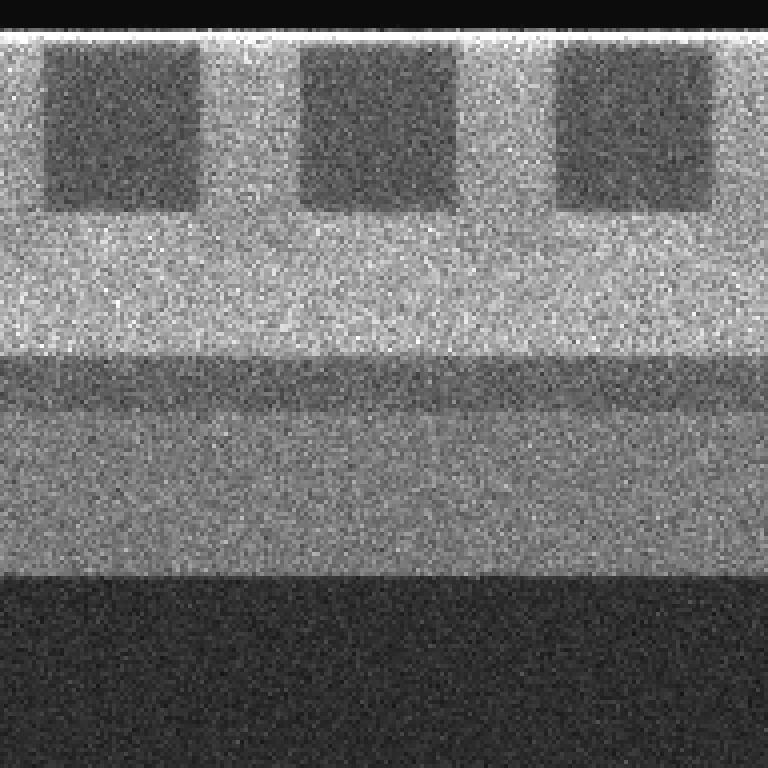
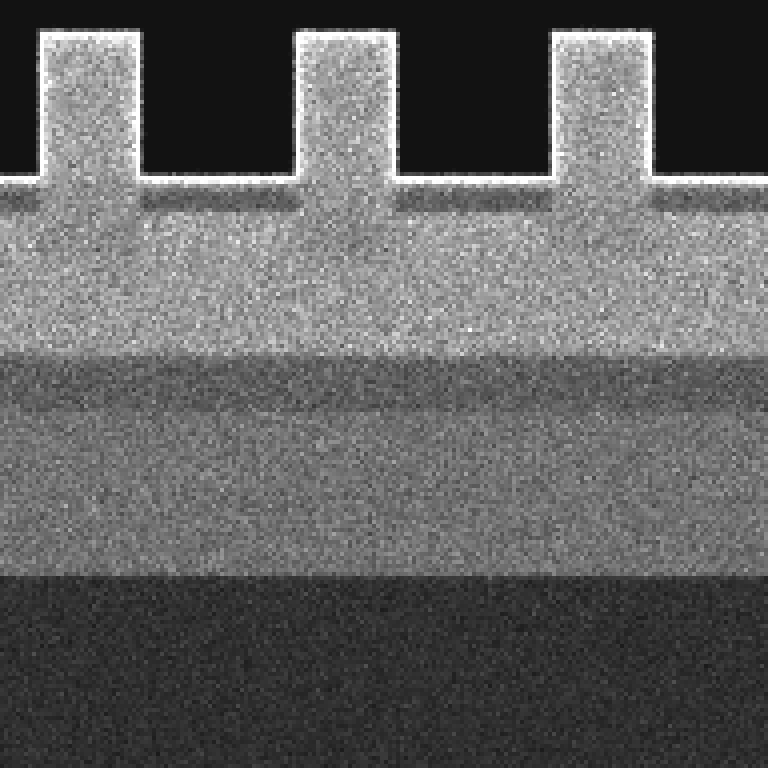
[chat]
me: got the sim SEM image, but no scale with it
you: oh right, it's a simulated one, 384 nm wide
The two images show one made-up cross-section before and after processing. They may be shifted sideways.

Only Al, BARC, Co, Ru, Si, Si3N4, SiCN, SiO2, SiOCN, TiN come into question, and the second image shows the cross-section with Si3N4 removed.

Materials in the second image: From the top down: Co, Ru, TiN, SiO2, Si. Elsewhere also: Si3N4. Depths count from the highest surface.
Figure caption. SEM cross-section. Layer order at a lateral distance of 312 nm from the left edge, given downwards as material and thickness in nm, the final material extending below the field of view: Co 112, Ru 50, TiN 28, SiO2 82, Si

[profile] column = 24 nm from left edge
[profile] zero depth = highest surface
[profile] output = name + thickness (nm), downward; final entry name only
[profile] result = Co 112, Ru 50, TiN 28, SiO2 82, Si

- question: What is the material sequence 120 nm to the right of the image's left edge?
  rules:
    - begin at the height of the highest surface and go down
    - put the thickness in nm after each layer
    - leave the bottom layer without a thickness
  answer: empty 72, Si3N4 18, Ru 72, TiN 28, SiO2 82, Si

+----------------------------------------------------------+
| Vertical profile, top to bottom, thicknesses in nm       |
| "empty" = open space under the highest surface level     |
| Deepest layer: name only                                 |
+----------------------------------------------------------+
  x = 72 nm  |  empty 72, Si3N4 18, Ru 72, TiN 28, SiO2 82, Si